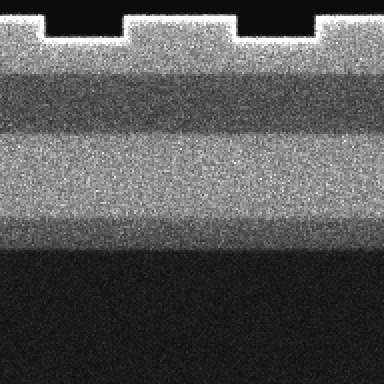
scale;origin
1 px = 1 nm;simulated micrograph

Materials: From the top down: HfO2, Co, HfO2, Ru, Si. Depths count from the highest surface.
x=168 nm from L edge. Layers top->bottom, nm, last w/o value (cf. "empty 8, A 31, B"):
HfO2 58, Co 60, HfO2 84, Ru 32, Si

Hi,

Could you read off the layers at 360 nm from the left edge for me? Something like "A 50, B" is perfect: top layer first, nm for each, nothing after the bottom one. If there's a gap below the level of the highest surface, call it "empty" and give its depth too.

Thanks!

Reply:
HfO2 58, Co 60, HfO2 84, Ru 32, Si